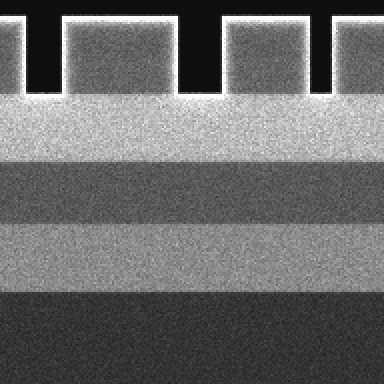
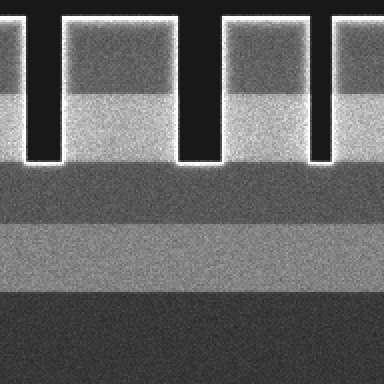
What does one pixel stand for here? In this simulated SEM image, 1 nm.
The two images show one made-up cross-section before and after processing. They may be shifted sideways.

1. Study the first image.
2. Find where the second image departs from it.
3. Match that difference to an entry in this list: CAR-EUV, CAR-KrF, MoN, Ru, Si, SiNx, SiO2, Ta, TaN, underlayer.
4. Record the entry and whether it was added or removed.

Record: Ru / removed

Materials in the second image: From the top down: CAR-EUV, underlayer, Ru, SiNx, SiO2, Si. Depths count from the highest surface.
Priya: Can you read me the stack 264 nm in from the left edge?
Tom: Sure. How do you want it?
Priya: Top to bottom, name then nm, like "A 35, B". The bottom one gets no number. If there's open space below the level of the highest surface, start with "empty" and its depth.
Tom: CAR-EUV 42, underlayer 36, Ru 68, SiNx 62, SiO2 68, Si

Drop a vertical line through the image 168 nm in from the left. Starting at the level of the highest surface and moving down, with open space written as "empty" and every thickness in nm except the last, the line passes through CAR-EUV 42, underlayer 36, Ru 68, SiNx 62, SiO2 68, Si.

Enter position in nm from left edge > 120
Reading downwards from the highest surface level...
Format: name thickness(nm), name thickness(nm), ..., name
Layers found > CAR-EUV 42, underlayer 36, Ru 68, SiNx 62, SiO2 68, Si